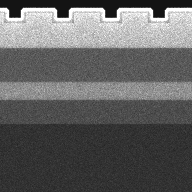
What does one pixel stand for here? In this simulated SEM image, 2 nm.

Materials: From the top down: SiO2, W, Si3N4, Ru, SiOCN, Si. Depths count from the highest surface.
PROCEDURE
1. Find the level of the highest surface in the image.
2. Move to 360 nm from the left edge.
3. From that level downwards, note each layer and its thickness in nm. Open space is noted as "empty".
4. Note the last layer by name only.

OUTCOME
SiO2 10, W 70, Si3N4 68, Ru 36, SiOCN 48, Si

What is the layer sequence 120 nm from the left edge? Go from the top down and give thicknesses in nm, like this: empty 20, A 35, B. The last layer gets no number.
empty 20, SiO2 10, W 50, Si3N4 68, Ru 36, SiOCN 48, Si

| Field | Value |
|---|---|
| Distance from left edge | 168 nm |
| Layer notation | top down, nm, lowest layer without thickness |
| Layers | SiO2 10, W 70, Si3N4 68, Ru 36, SiOCN 48, Si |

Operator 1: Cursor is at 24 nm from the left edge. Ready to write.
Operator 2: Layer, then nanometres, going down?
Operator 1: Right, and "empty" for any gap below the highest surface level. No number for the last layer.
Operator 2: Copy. empty 20, SiO2 10, W 50, Si3N4 68, Ru 36, SiOCN 48, Si